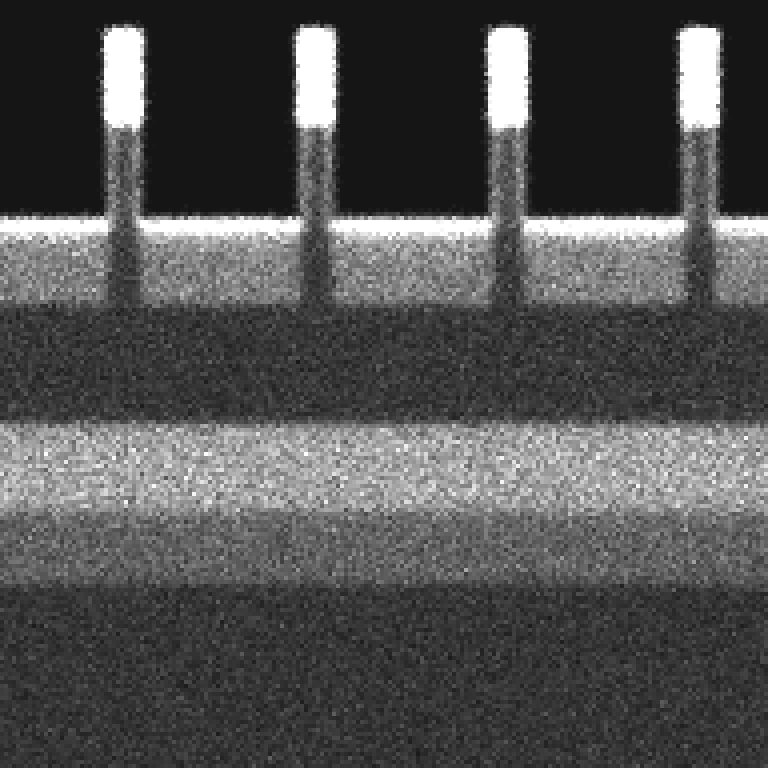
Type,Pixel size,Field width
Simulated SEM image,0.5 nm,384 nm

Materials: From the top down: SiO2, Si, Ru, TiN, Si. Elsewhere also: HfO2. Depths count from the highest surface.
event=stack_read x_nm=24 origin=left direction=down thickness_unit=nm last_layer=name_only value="empty 94, SiO2 42, Si 60, Ru 44, TiN 36, Si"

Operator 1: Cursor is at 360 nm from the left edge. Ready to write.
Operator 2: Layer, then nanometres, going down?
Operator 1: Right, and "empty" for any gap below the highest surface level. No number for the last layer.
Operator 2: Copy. empty 94, SiO2 42, Si 60, Ru 44, TiN 36, Si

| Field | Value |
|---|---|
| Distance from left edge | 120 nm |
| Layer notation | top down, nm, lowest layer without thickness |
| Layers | empty 94, SiO2 42, Si 60, Ru 44, TiN 36, Si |